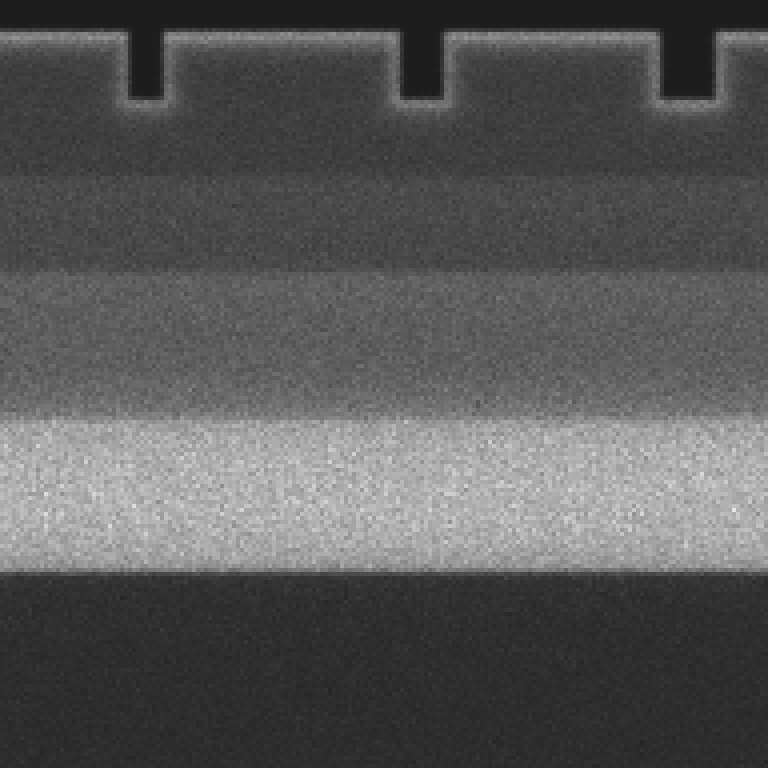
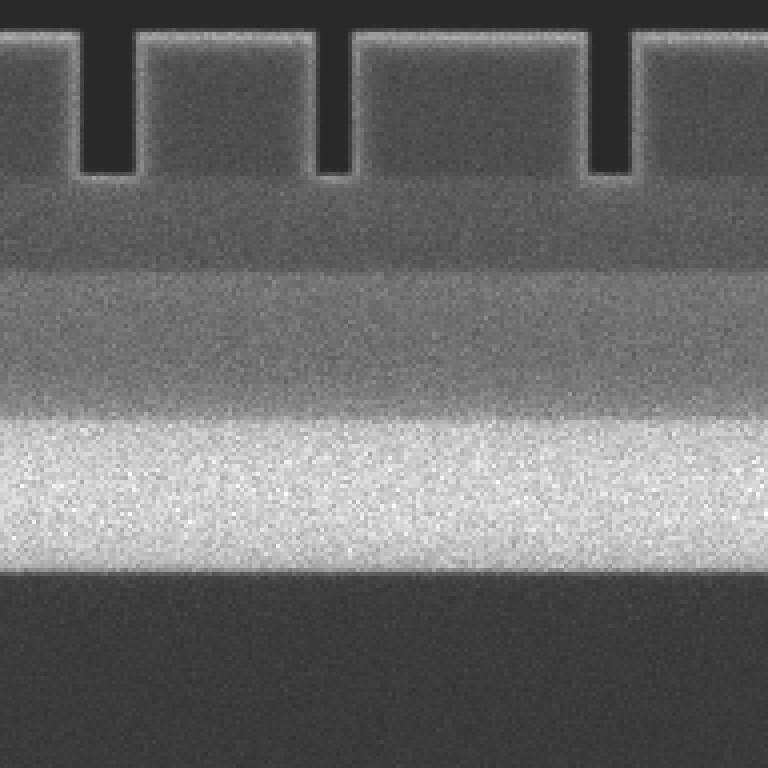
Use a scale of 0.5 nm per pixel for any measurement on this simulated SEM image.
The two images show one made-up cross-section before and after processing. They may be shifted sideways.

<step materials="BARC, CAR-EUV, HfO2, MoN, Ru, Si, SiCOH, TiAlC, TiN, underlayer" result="removed underlayer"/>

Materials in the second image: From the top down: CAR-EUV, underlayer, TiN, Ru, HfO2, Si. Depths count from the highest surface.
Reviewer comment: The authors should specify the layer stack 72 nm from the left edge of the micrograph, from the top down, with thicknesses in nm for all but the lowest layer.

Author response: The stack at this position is CAR-EUV 34, underlayer 38, TiN 48, Ru 74, HfO2 76, Si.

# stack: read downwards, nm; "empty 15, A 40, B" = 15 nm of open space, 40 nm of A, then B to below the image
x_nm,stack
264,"CAR-EUV 34, underlayer 38, TiN 48, Ru 74, HfO2 76, Si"